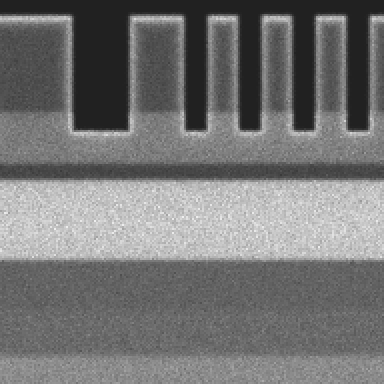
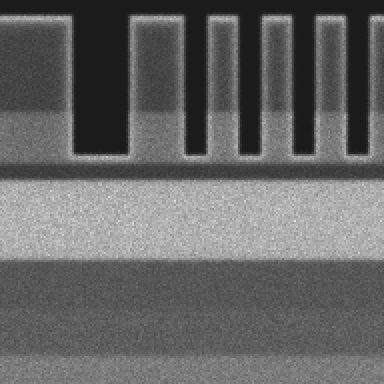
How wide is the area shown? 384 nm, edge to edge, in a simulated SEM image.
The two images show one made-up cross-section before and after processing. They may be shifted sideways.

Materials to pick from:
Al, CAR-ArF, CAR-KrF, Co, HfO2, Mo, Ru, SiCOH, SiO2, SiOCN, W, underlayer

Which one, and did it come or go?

Ru - removed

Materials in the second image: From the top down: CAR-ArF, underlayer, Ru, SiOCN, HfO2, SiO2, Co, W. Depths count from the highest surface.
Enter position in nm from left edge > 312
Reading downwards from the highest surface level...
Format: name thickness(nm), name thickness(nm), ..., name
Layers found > empty 140, Ru 8, SiOCN 16, HfO2 80, SiO2 50, Co 46, W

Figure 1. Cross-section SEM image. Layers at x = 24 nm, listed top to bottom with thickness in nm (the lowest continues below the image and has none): CAR-ArF 46, underlayer 50, Ru 52, SiOCN 16, HfO2 80, SiO2 50, Co 46, W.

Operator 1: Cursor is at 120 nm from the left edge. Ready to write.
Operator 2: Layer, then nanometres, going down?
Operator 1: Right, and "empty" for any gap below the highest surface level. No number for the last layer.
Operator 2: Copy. empty 140, Ru 8, SiOCN 16, HfO2 80, SiO2 50, Co 46, W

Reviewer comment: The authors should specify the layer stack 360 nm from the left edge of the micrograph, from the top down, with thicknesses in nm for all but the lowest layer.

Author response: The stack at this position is empty 140, Ru 8, SiOCN 16, HfO2 80, SiO2 50, Co 46, W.